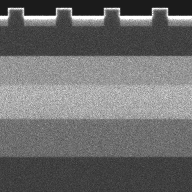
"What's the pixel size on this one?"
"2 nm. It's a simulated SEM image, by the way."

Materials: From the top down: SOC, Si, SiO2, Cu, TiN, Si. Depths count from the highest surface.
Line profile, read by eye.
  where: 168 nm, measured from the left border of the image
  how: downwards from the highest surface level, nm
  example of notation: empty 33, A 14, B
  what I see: empty 16, SOC 20, Si 60, SiO2 58, Cu 68, TiN 76, Si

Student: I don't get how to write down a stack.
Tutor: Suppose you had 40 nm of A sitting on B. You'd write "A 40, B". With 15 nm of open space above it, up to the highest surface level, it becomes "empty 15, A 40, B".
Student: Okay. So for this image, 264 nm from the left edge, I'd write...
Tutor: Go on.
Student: empty 16, SOC 20, Si 60, SiO2 58, Cu 68, TiN 76, Si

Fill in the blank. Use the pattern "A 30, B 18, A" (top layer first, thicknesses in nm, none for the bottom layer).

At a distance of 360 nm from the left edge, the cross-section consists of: empty 16, SOC 20, Si 60, SiO2 58, Cu 68, TiN 76, Si